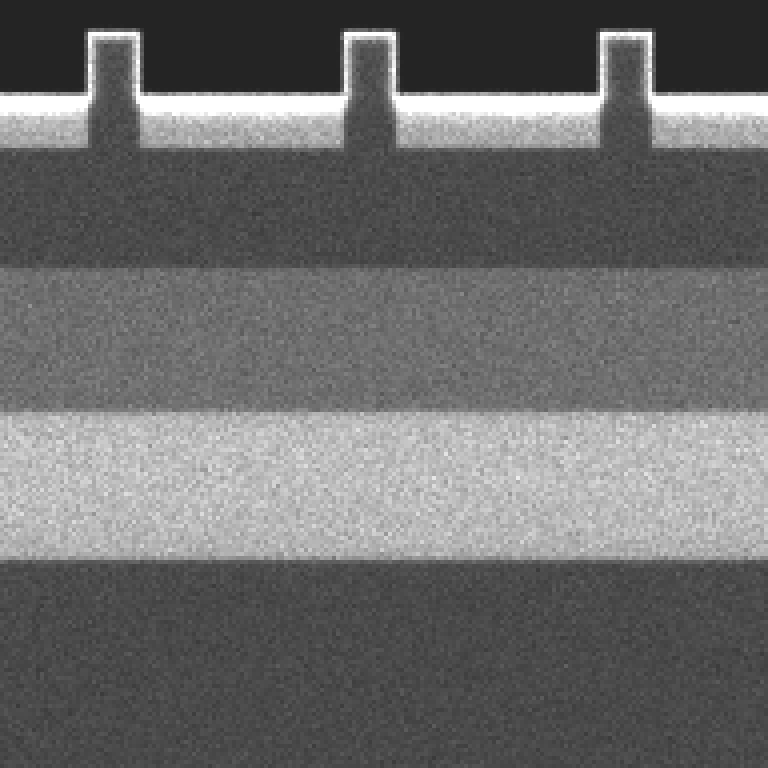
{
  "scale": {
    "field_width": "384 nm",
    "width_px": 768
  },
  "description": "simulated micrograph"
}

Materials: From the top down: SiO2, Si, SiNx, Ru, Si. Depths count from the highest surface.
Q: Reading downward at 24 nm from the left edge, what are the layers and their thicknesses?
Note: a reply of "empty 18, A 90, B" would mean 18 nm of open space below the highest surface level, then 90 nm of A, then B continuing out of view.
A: empty 32, SiO2 26, Si 60, SiNx 72, Ru 74, Si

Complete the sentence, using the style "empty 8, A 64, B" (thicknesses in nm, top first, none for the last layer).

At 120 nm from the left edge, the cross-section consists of empty 32, SiO2 26, Si 60, SiNx 72, Ru 74, Si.